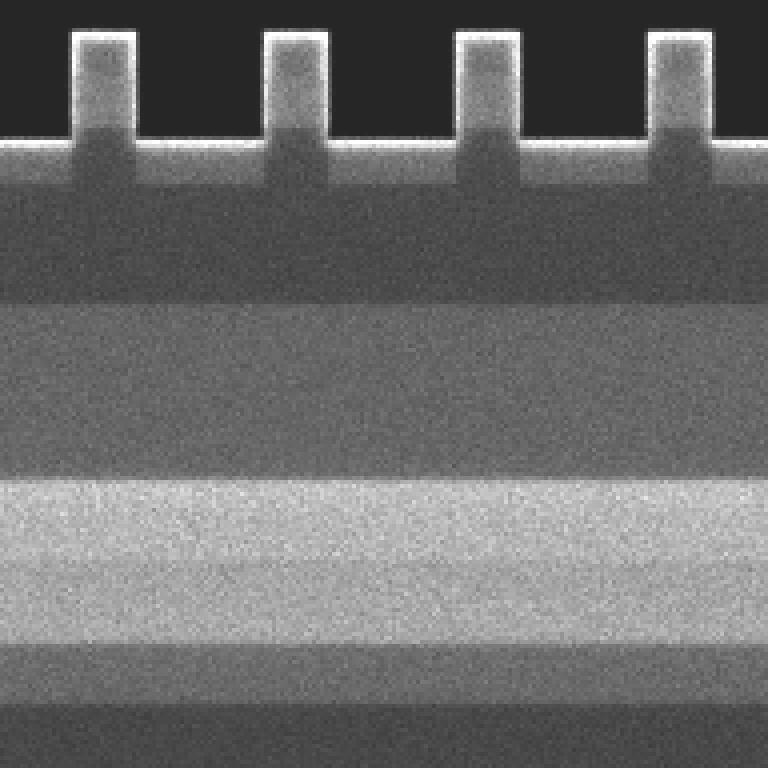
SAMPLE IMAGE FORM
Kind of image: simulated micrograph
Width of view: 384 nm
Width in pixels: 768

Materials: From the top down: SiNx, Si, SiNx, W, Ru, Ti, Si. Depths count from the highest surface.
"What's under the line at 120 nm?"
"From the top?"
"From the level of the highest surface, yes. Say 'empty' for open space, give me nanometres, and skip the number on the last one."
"empty 54, SiNx 22, Si 60, SiNx 88, W 40, Ru 42, Ti 30, Si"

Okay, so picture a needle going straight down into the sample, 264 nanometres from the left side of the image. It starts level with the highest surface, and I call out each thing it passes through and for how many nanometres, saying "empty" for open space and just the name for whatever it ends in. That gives empty 54, SiNx 22, Si 60, SiNx 88, W 40, Ru 42, Ti 30, Si